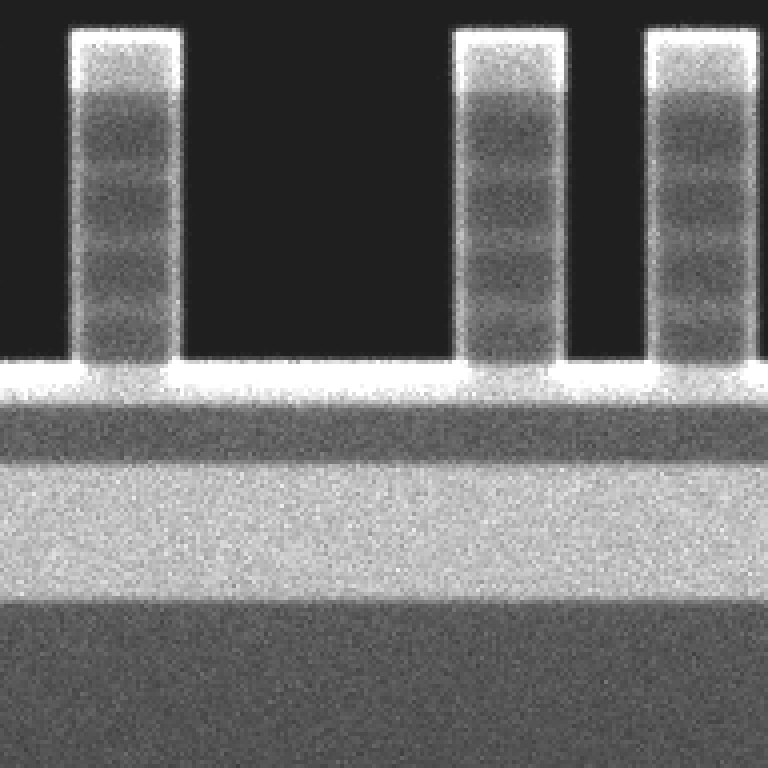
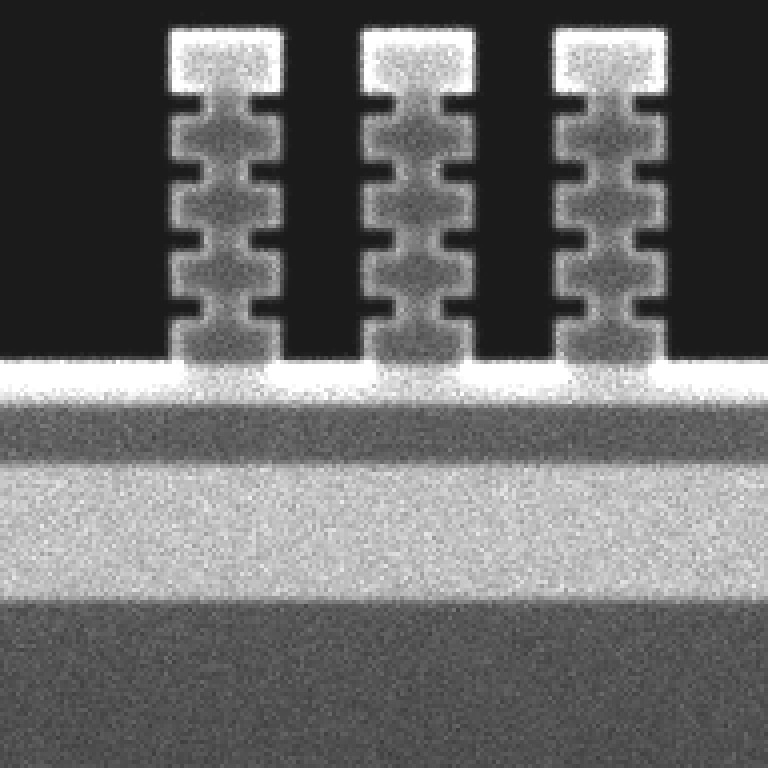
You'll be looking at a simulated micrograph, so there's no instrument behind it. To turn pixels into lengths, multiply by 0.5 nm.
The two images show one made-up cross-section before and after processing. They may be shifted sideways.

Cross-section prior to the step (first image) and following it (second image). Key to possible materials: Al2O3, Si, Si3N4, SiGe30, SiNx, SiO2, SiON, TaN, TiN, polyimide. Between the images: SiGe30 was removed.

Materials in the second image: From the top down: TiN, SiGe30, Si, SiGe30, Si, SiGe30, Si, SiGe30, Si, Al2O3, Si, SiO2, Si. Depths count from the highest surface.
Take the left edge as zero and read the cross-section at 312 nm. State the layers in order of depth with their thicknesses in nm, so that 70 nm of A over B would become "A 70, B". TiN 30, SiGe30 12, Si 22, SiGe30 12, Si 22, SiGe30 12, Si 22, SiGe30 12, Si 22, Al2O3 20, Si 30, SiO2 68, Si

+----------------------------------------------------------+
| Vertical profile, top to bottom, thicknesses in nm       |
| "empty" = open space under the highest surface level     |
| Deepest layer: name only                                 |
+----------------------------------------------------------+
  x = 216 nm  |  TiN 30, SiGe30 12, Si 22, SiGe30 12, Si 22, SiGe30 12, Si 22, SiGe30 12, Si 22, Al2O3 20, Si 30, SiO2 68, Si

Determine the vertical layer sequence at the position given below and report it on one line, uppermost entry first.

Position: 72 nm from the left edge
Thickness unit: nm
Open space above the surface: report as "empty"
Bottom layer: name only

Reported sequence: empty 166, Al2O3 20, Si 30, SiO2 68, Si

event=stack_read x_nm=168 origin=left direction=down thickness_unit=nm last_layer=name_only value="empty 166, Al2O3 20, Si 30, SiO2 68, Si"